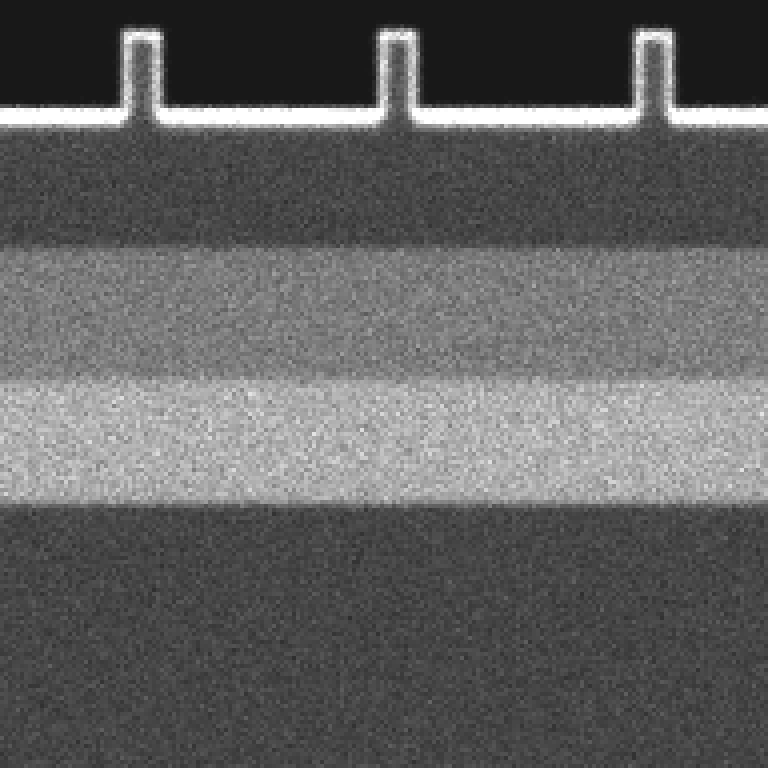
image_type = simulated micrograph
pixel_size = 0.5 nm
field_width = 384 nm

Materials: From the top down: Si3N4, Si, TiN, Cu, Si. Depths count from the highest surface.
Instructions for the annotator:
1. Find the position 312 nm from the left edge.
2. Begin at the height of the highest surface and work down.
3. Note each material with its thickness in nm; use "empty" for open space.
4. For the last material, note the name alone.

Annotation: empty 40, Si3N4 8, Si 60, TiN 66, Cu 62, Si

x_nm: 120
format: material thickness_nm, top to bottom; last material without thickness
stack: empty 40, Si3N4 8, Si 60, TiN 66, Cu 62, Si